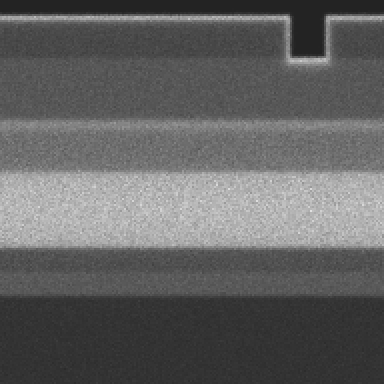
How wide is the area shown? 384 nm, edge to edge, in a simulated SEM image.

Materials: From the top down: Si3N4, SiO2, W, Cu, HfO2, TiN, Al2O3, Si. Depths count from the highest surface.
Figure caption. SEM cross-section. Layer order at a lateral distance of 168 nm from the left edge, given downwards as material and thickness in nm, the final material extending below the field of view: Si3N4 42, SiO2 62, W 10, Cu 42, HfO2 76, TiN 24, Al2O3 24, Si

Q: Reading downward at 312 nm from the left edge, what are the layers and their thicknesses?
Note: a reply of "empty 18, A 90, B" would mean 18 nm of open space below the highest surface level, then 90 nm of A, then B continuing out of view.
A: empty 42, SiO2 62, W 10, Cu 42, HfO2 76, TiN 24, Al2O3 24, Si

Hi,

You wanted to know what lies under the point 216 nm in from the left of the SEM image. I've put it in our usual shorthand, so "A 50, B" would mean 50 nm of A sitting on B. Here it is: Si3N4 42, SiO2 62, W 10, Cu 42, HfO2 76, TiN 24, Al2O3 24, Si